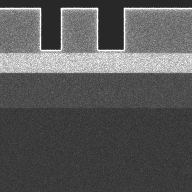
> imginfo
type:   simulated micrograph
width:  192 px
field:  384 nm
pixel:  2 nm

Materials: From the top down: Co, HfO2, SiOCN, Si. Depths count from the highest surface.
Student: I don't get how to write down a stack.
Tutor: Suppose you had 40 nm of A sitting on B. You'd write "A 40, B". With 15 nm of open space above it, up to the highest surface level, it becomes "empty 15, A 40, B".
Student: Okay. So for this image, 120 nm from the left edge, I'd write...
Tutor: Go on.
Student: empty 84, Co 6, HfO2 40, SiOCN 70, Si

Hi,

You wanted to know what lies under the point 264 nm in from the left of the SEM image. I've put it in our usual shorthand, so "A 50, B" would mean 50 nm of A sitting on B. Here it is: Co 90, HfO2 40, SiOCN 70, Si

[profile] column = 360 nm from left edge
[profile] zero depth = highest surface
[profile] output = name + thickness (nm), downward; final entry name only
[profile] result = Co 90, HfO2 40, SiOCN 70, Si